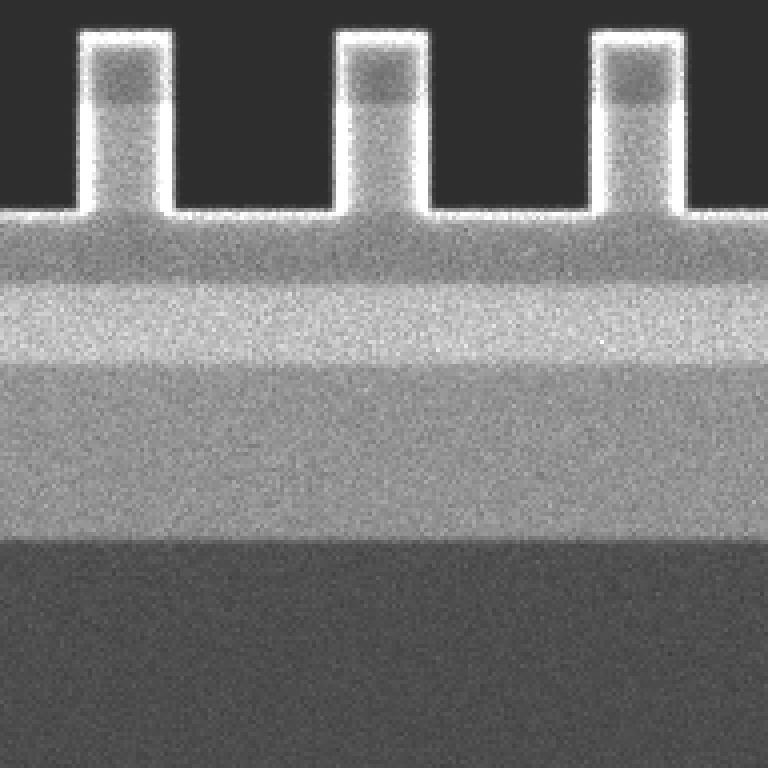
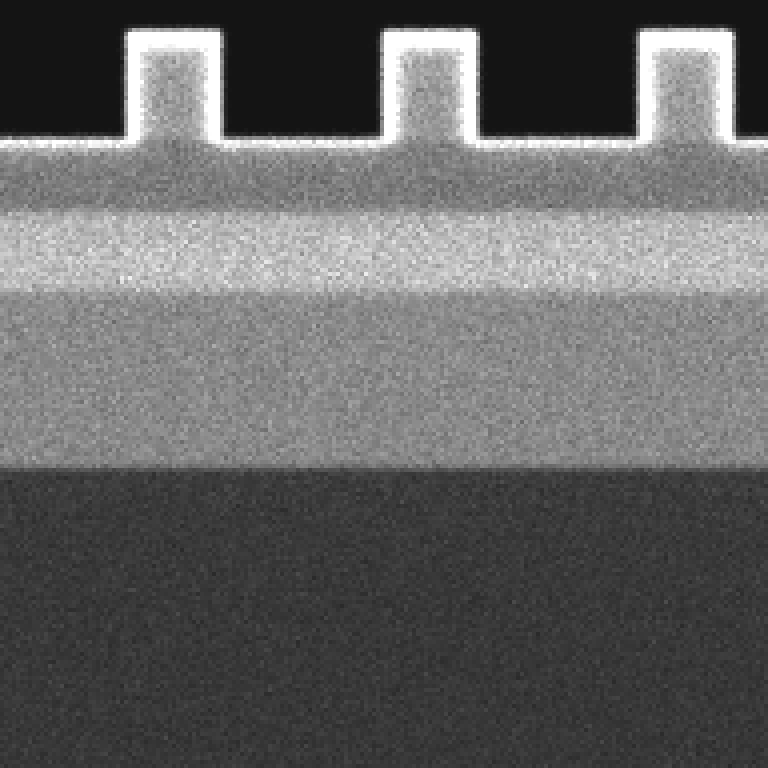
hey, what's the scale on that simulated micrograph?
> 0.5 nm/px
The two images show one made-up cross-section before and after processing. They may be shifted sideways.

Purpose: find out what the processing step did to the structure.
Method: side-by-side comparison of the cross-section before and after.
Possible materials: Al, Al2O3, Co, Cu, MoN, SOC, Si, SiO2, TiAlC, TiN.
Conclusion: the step removed SOC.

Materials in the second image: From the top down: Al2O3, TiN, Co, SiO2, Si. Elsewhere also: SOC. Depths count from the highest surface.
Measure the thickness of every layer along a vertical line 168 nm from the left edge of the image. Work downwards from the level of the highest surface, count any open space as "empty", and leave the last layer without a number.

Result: empty 54, TiN 36, Co 40, SiO2 88, Si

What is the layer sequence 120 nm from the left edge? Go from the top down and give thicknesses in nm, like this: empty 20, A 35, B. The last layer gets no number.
empty 54, TiN 36, Co 40, SiO2 88, Si